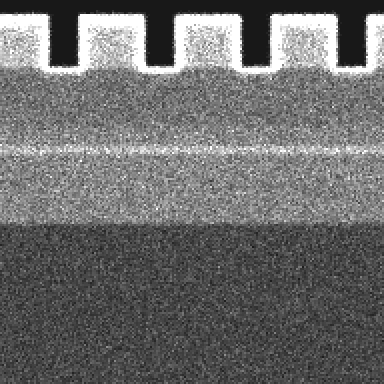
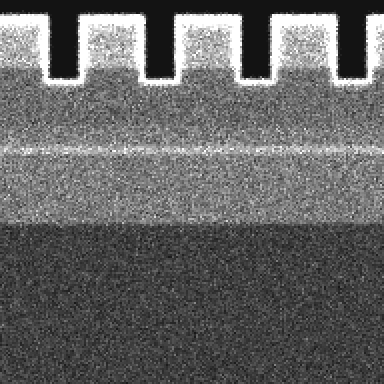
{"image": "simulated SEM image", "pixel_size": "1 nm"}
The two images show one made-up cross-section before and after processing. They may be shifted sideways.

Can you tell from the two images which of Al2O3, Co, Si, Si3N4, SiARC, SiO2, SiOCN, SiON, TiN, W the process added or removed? Yes, it removed SiOCN.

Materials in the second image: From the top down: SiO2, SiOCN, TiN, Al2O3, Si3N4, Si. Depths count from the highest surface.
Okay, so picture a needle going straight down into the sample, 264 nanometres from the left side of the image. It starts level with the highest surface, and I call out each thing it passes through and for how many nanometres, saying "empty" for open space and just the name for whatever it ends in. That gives empty 64, SiOCN 46, TiN 20, Al2O3 8, Si3N4 70, Si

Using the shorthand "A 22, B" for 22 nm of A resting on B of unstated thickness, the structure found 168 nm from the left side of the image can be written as empty 64, SiOCN 46, TiN 20, Al2O3 8, Si3N4 70, Si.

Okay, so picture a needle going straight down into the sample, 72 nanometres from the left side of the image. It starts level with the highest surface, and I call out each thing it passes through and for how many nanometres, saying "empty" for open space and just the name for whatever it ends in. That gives empty 64, SiOCN 46, TiN 20, Al2O3 8, Si3N4 70, Si